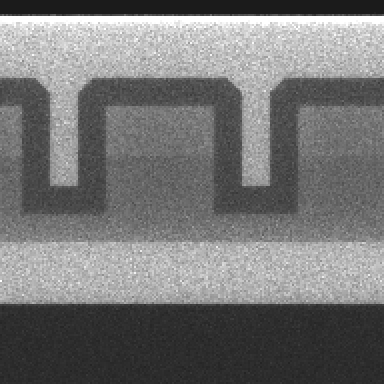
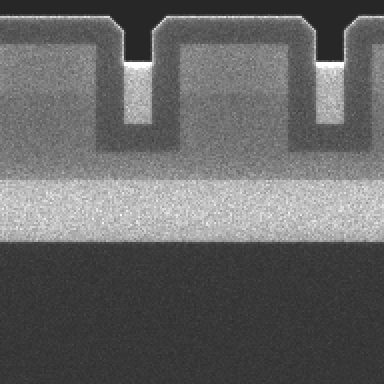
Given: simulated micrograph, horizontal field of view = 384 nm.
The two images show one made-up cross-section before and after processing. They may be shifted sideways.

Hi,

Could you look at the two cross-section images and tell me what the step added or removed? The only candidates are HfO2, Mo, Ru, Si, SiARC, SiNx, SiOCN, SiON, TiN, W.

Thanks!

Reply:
removed HfO2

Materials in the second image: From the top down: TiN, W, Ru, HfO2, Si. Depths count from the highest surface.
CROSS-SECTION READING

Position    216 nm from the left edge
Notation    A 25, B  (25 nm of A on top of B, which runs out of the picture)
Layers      TiN 28, W 50, Ru 86, HfO2 62, Si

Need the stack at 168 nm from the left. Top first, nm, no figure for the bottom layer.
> TiN 136, Ru 28, HfO2 62, Si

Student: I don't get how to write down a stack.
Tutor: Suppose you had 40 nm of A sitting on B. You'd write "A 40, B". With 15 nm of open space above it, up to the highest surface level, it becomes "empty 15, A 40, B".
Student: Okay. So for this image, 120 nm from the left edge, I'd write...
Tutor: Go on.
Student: empty 12, TiN 124, Ru 28, HfO2 62, Si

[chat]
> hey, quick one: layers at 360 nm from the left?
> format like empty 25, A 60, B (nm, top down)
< TiN 136, Ru 28, HfO2 62, Si